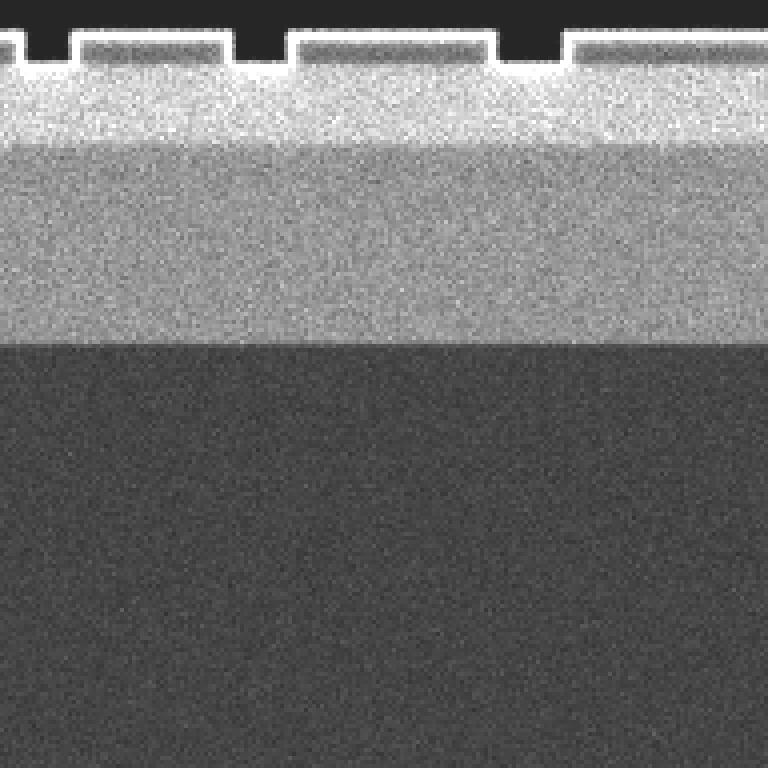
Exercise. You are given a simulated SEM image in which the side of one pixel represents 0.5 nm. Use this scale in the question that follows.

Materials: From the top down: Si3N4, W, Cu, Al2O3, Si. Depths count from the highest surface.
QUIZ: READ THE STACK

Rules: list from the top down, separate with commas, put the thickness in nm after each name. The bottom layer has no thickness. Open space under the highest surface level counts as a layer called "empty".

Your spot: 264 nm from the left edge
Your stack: empty 16, W 40, Cu 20, Al2O3 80, Si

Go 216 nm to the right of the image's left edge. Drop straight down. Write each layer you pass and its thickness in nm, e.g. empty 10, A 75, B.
Si3N4 16, W 40, Cu 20, Al2O3 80, Si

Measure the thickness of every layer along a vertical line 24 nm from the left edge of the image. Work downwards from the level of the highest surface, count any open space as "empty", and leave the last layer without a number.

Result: empty 16, W 40, Cu 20, Al2O3 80, Si